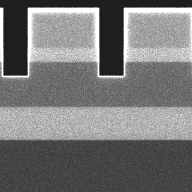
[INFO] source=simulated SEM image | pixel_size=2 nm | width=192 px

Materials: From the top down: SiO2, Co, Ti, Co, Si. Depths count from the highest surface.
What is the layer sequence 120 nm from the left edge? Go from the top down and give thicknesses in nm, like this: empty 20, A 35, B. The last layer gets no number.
SiO2 80, Co 28, Ti 90, Co 66, Si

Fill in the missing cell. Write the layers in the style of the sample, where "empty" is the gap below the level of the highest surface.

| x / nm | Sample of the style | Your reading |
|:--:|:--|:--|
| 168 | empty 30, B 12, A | SiO2 80, Co 28, Ti 90, Co 66, Si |